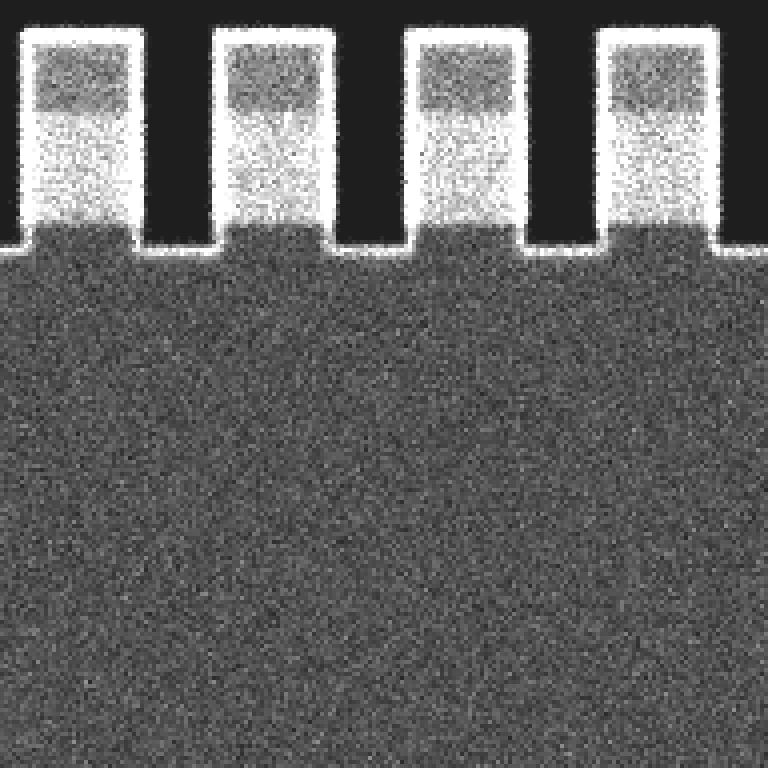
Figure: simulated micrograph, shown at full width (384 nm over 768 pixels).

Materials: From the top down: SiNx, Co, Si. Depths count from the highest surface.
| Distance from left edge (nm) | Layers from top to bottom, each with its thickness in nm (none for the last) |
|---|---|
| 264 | empty 108, Si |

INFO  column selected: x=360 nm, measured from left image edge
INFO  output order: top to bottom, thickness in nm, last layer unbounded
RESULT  empty 108, Si